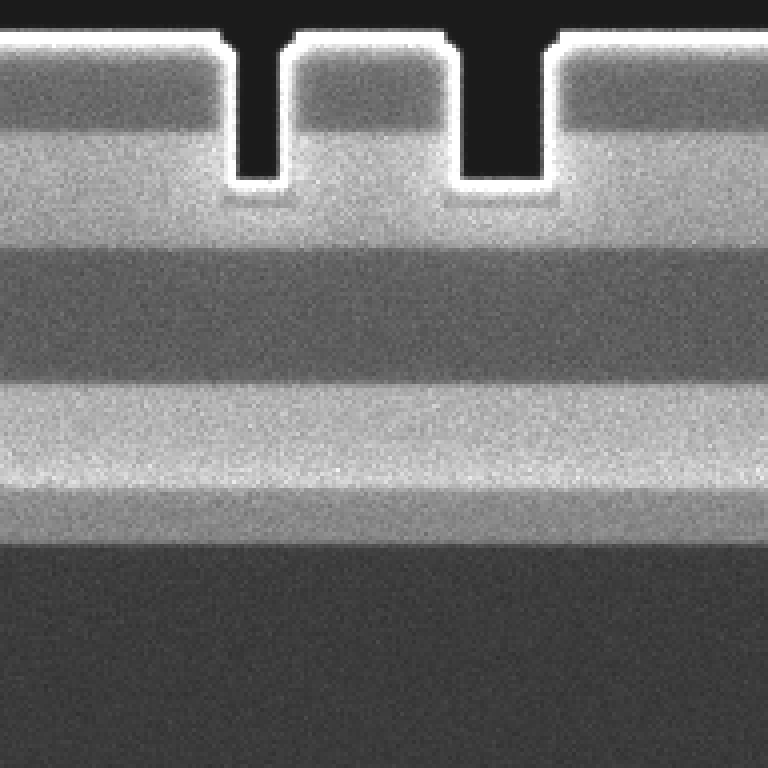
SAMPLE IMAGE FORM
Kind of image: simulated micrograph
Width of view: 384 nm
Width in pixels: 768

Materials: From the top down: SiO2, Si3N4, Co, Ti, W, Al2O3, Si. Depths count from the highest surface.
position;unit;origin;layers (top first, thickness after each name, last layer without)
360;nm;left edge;SiO2 14, Si3N4 36, Co 58, Ti 68, W 52, Al2O3 28, Si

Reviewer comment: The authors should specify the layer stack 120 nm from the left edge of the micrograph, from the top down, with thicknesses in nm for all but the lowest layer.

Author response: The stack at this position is empty 74, SiO2 14, Co 20, Ti 68, W 52, Al2O3 28, Si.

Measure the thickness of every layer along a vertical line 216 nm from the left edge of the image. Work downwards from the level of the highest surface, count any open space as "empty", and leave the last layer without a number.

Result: SiO2 14, Si3N4 36, Co 58, Ti 68, W 52, Al2O3 28, Si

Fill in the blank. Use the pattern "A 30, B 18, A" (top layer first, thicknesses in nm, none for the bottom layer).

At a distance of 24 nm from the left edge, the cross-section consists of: SiO2 14, Si3N4 36, Co 58, Ti 68, W 52, Al2O3 28, Si